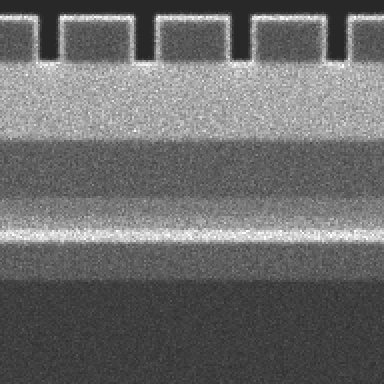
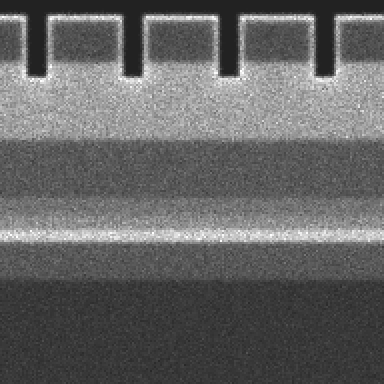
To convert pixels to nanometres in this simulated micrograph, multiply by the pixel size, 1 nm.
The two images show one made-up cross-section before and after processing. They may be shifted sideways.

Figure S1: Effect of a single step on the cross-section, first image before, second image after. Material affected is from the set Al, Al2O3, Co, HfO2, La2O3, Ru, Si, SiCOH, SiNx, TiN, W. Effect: removed W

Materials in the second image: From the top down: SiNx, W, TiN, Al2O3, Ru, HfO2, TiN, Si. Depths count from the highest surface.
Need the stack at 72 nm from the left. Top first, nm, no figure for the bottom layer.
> SiNx 46, W 78, TiN 58, Al2O3 18, Ru 14, HfO2 12, TiN 38, Si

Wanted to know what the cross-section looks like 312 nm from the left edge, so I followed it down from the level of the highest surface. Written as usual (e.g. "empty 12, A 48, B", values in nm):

SiNx 46, W 78, TiN 58, Al2O3 18, Ru 14, HfO2 12, TiN 38, Si